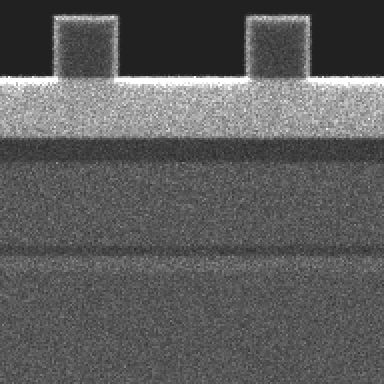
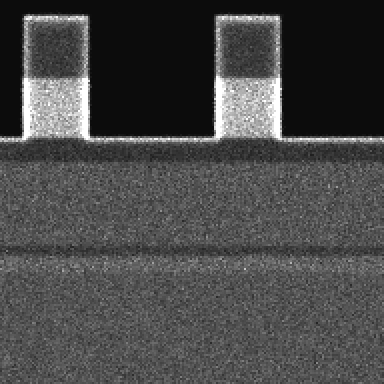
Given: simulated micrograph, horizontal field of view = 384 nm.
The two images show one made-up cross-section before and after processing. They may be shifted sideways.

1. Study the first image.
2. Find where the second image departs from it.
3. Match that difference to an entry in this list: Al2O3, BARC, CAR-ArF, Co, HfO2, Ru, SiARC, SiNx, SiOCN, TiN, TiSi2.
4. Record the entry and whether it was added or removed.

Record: HfO2 / removed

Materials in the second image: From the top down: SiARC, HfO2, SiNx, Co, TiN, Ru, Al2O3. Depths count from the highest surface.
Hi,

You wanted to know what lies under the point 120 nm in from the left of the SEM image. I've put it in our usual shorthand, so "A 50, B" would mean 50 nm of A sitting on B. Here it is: empty 122, SiNx 24, Co 84, TiN 10, Ru 16, Al2O3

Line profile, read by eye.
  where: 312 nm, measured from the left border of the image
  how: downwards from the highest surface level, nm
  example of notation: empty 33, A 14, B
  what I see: empty 122, SiNx 24, Co 84, TiN 10, Ru 16, Al2O3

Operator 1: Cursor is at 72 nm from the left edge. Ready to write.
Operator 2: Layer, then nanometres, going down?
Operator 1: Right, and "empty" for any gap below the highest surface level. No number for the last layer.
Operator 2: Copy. SiARC 62, HfO2 60, SiNx 24, Co 84, TiN 10, Ru 16, Al2O3